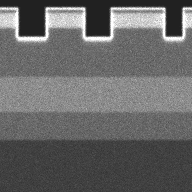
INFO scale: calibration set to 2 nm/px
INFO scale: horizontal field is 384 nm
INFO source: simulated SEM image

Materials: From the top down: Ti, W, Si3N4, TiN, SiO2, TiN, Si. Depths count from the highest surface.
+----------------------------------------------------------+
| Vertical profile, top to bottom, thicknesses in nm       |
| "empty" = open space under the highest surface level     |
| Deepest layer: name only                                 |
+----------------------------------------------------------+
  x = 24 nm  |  Ti 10, W 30, Si3N4 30, TiN 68, SiO2 70, TiN 56, Si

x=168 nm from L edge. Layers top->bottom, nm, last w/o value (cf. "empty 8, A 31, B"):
Ti 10, W 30, Si3N4 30, TiN 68, SiO2 70, TiN 56, Si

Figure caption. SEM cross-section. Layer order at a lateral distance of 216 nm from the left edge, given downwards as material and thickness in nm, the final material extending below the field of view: empty 58, Si3N4 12, TiN 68, SiO2 70, TiN 56, Si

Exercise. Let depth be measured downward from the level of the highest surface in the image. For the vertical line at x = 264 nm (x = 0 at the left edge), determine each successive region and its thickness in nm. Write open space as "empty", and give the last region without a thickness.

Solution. Ti 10, W 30, Si3N4 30, TiN 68, SiO2 70, TiN 56, Si